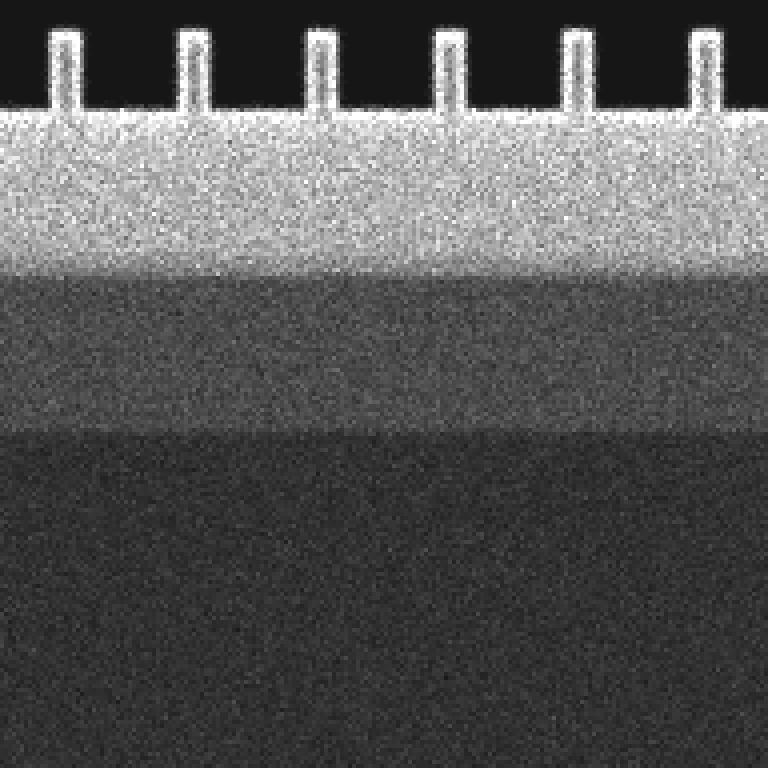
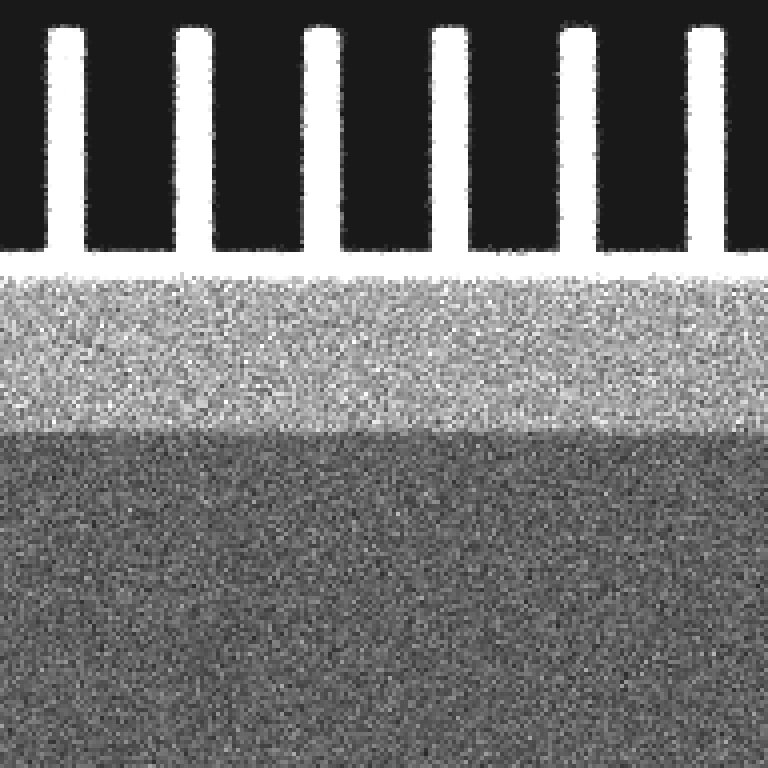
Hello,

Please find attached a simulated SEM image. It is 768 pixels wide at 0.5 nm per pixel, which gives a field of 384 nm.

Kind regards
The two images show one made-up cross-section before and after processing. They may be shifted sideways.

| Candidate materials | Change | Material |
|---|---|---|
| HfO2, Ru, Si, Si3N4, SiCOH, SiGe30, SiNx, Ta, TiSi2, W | removed | W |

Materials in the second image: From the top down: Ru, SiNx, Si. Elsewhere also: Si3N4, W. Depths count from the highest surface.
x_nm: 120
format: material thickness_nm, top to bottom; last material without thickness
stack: empty 112, Ru 10, SiNx 78, Si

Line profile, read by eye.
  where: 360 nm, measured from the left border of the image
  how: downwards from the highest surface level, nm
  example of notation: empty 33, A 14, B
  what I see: empty 112, Ru 10, SiNx 78, Si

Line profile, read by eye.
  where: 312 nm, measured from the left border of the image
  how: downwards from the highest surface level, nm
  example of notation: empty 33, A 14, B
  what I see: empty 112, Ru 10, SiNx 78, Si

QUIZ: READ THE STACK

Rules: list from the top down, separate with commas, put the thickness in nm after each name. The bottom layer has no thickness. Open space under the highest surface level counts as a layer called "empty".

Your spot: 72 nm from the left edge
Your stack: empty 112, Ru 10, SiNx 78, Si